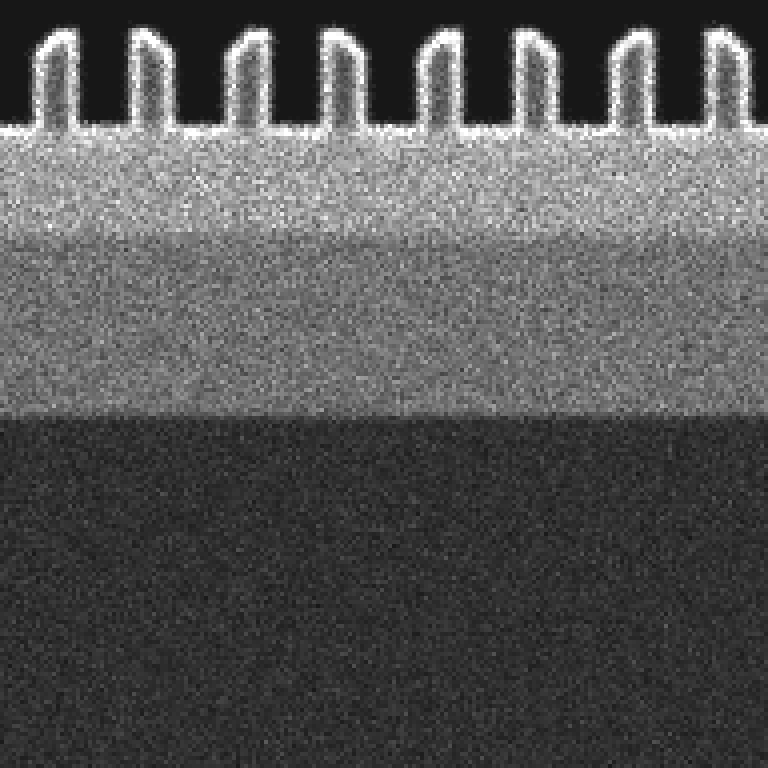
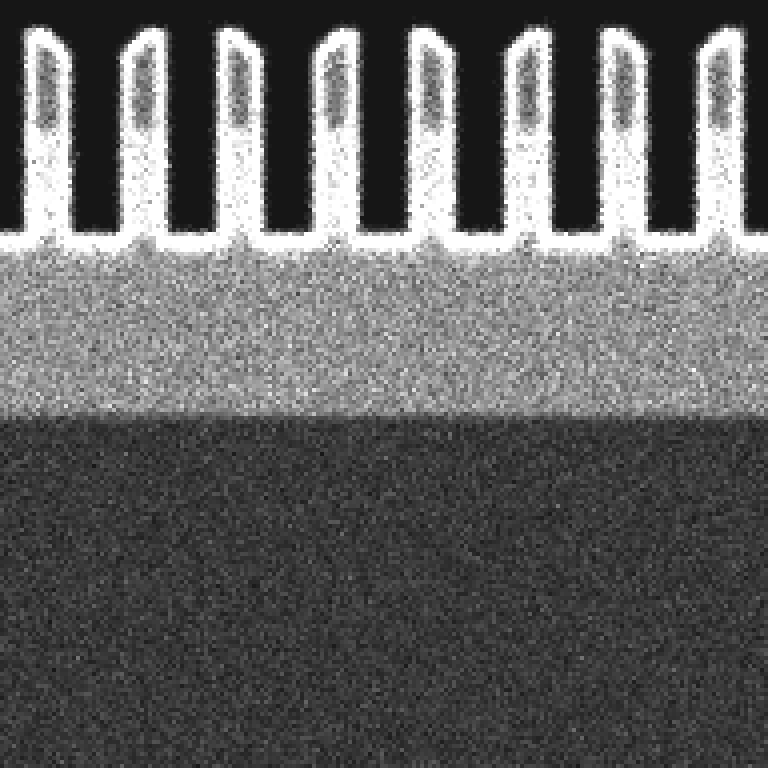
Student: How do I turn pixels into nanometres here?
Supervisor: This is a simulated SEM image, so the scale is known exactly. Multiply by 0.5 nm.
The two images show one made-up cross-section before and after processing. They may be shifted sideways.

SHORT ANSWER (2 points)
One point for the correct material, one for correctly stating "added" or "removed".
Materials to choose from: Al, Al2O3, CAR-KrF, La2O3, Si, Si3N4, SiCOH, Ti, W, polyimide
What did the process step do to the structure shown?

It removed W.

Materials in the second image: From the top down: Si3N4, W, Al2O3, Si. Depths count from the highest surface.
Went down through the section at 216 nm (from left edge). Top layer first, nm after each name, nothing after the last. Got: empty 2, Si3N4 46, W 54, Al2O3 90, Si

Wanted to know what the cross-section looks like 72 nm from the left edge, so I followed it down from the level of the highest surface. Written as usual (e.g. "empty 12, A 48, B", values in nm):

Si3N4 48, W 54, Al2O3 90, Si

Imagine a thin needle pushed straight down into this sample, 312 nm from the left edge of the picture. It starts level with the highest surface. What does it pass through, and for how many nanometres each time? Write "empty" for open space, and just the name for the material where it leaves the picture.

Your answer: empty 2, Si3N4 46, W 54, Al2O3 90, Si